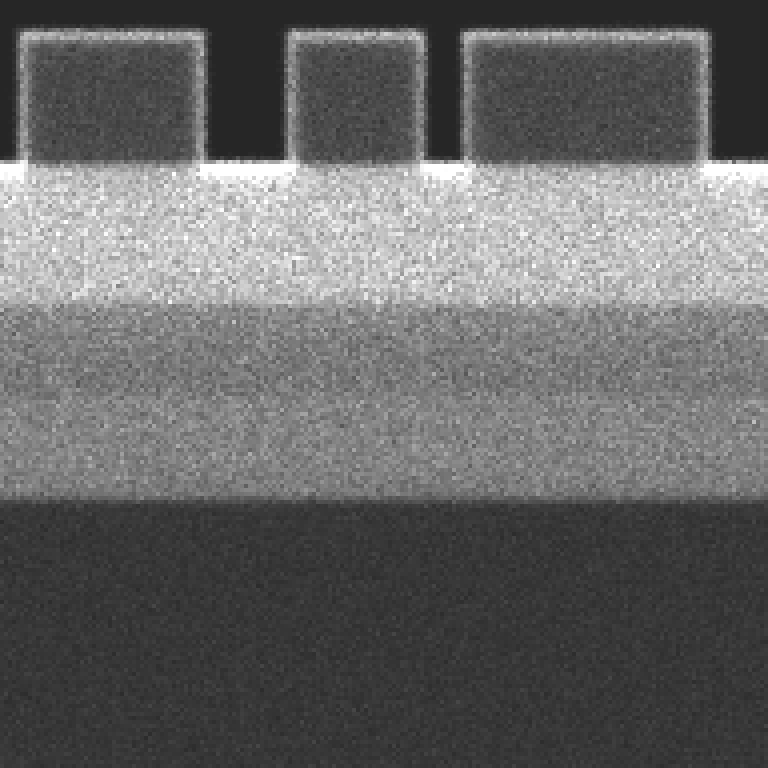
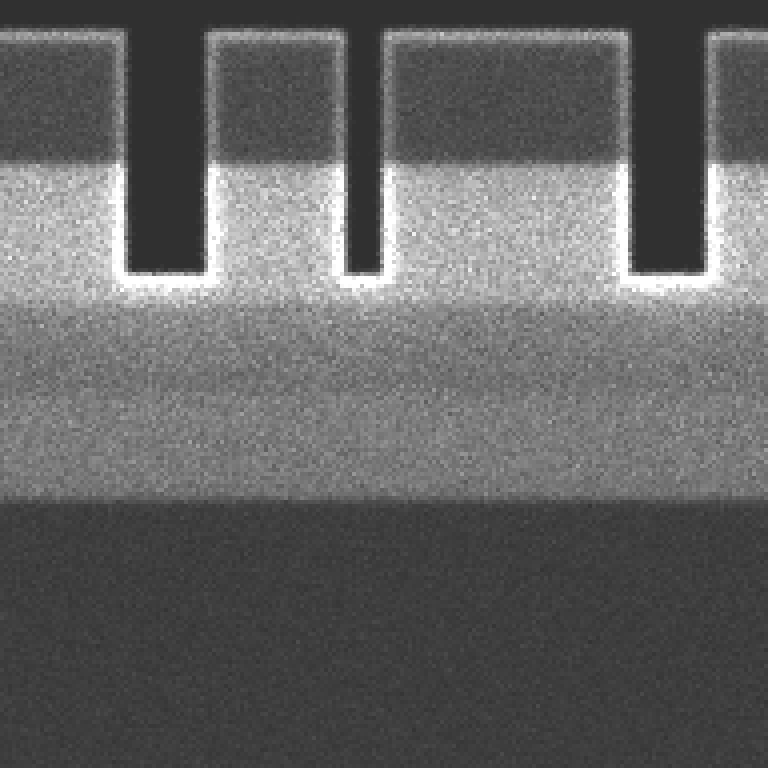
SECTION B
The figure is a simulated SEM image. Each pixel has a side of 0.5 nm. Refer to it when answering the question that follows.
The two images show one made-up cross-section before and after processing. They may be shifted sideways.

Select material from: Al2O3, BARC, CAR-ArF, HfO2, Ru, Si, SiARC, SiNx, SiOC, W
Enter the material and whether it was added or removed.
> HfO2 / removed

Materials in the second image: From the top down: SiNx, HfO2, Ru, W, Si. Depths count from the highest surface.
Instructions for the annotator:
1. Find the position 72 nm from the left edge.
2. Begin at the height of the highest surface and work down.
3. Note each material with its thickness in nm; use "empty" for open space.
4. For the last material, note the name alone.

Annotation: empty 122, HfO2 14, Ru 46, W 52, Si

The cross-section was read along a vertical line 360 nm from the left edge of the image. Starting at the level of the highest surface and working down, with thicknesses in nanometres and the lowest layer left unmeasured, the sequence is SiNx 66, HfO2 70, Ru 46, W 52, Si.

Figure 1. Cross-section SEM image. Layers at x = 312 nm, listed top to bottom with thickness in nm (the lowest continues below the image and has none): SiNx 66, HfO2 70, Ru 46, W 52, Si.